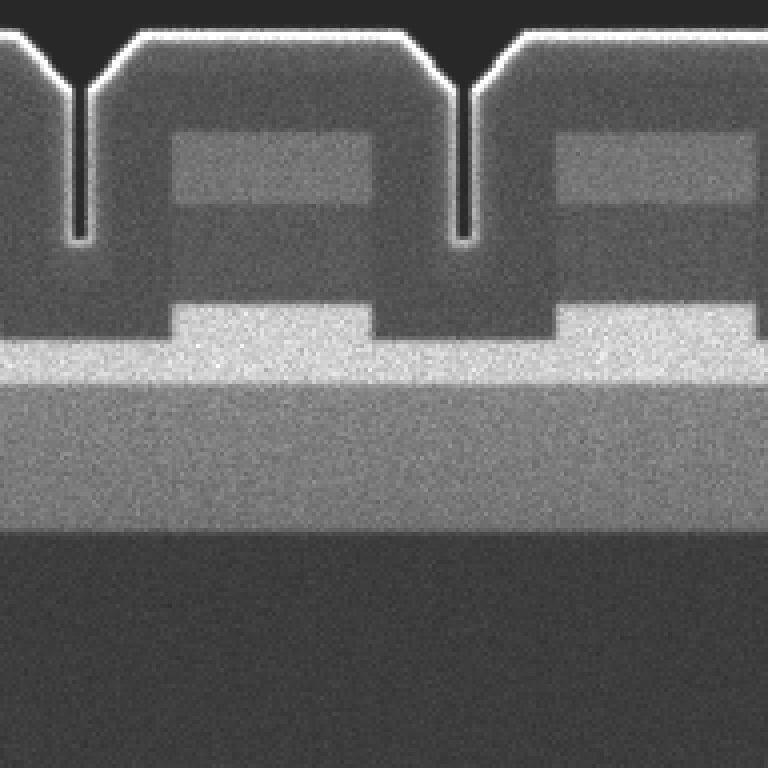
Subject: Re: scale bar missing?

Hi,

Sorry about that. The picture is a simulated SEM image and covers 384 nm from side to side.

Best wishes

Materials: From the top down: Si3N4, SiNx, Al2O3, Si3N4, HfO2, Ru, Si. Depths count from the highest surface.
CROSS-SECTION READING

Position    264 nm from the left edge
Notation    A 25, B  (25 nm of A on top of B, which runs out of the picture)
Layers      Si3N4 20, SiNx 134, HfO2 22, Ru 74, Si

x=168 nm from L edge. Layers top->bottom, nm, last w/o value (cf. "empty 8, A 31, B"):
Si3N4 20, SiNx 30, Al2O3 36, Si3N4 50, HfO2 40, Ru 74, Si